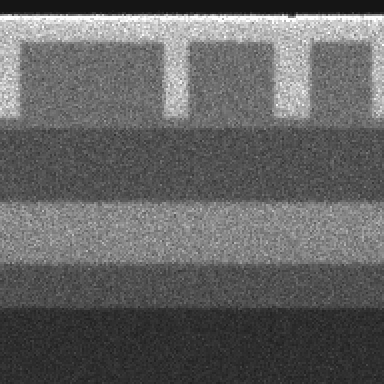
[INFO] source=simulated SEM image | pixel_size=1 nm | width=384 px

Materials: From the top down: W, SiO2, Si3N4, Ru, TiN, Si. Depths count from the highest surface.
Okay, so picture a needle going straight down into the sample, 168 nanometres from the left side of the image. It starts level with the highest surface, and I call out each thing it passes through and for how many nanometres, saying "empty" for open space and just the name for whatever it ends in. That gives W 102, SiO2 10, Si3N4 74, Ru 62, TiN 44, Si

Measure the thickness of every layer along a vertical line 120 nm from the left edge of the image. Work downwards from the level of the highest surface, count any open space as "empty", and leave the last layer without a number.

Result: W 26, SiO2 86, Si3N4 74, Ru 62, TiN 44, Si